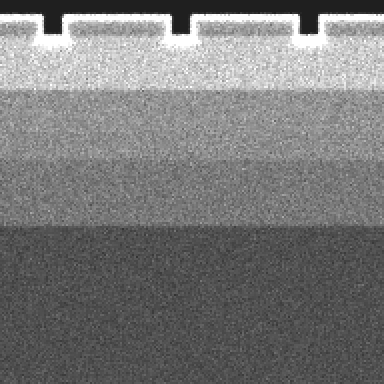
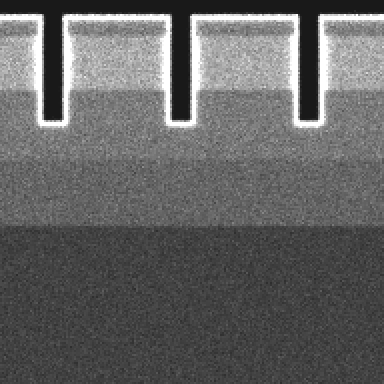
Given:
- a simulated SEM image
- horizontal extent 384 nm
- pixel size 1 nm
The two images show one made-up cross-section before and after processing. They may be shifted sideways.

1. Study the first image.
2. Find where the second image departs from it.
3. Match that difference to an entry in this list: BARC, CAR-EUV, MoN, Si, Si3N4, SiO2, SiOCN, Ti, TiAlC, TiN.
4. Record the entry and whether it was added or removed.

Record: Si3N4 and SiO2 / removed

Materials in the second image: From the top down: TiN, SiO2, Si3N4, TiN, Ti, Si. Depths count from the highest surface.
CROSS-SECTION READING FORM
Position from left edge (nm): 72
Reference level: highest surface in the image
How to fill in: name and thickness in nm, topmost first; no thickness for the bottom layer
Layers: TiN 20, SiO2 54, Si3N4 42, TiN 28, Ti 66, Si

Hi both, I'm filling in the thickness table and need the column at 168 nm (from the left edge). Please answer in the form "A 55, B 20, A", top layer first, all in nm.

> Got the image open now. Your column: TiN 20, SiO2 54, Si3N4 42, TiN 28, Ti 66, Si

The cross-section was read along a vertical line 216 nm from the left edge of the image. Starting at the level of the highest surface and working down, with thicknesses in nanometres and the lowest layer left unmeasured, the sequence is TiN 20, SiO2 54, Si3N4 42, TiN 28, Ti 66, Si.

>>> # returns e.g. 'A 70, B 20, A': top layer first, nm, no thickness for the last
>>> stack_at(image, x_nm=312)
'empty 106, Si3N4 10, TiN 28, Ti 66, Si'